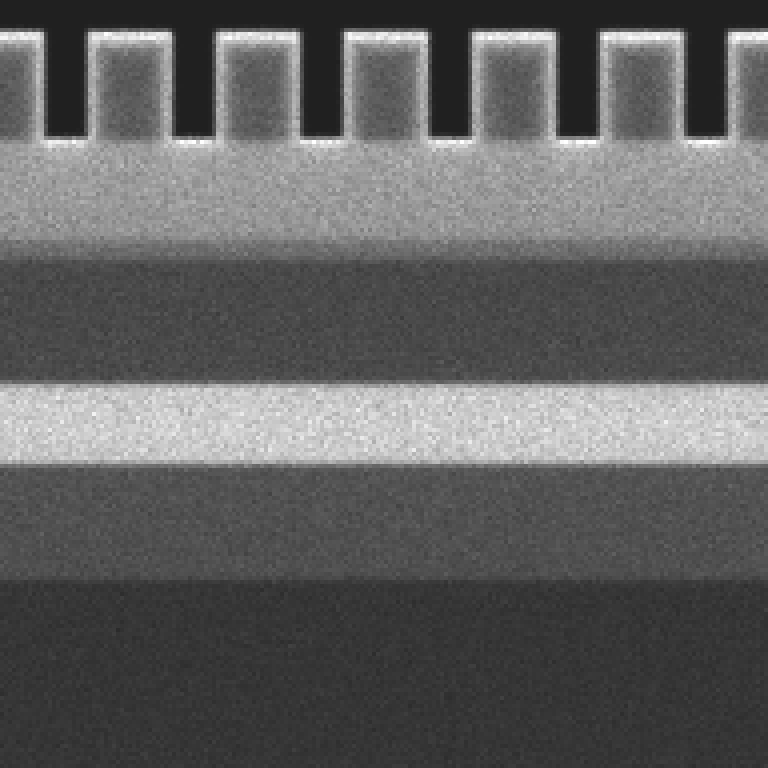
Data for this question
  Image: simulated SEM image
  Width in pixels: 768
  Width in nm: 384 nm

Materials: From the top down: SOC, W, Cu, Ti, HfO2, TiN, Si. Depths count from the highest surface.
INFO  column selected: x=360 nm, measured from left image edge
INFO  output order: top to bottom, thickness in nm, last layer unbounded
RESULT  empty 54, W 50, Cu 10, Ti 62, HfO2 40, TiN 58, Si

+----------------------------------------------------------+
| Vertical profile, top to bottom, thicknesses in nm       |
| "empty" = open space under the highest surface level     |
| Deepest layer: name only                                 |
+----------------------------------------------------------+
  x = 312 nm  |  SOC 54, W 50, Cu 10, Ti 62, HfO2 40, TiN 58, Si